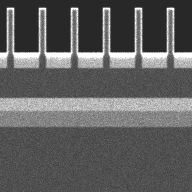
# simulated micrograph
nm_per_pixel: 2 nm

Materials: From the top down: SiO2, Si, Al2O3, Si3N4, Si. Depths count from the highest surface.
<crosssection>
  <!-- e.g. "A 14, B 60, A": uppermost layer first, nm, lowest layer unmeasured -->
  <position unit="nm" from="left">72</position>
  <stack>empty 90, SiO2 30, Si 60, Al2O3 26, Si3N4 32, Si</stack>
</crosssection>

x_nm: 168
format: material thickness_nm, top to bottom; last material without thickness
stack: empty 90, SiO2 30, Si 60, Al2O3 26, Si3N4 32, Si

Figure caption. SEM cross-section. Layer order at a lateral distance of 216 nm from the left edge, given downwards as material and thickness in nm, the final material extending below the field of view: Si 180, Al2O3 26, Si3N4 32, Si